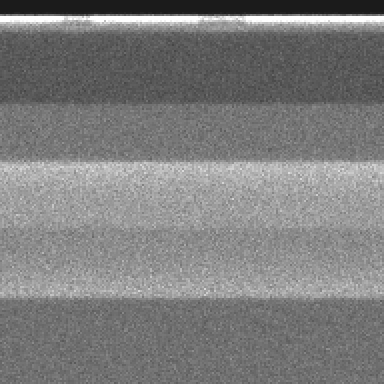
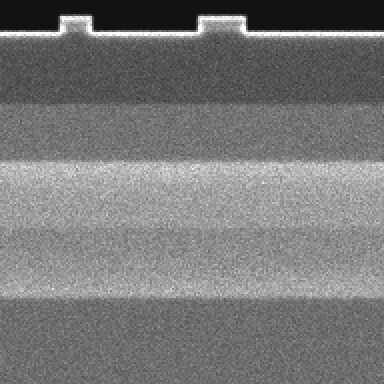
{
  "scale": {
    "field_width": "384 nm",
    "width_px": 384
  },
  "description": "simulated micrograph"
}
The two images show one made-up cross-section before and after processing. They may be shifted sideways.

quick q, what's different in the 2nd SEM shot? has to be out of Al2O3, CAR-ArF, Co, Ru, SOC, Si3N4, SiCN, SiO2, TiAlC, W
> Al2O3 removed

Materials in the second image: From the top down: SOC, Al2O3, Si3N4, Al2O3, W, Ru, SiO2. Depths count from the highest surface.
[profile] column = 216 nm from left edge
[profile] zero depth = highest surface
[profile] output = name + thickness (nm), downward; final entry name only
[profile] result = SOC 10, Al2O3 6, Si3N4 72, Al2O3 58, W 66, Ru 70, SiO2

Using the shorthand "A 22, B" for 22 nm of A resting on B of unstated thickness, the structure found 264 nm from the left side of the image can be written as empty 16, Si3N4 72, Al2O3 58, W 66, Ru 70, SiO2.